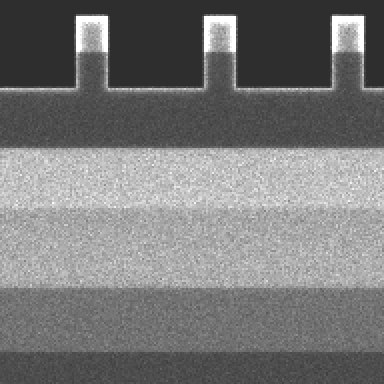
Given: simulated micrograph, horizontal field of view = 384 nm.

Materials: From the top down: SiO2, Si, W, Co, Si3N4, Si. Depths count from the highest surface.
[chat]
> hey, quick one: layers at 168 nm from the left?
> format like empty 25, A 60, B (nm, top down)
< empty 72, Si 60, W 60, Co 80, Si3N4 64, Si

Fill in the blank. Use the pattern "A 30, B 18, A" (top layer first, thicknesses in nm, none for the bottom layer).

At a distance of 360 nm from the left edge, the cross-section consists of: SiO2 36, Si 96, W 60, Co 80, Si3N4 64, Si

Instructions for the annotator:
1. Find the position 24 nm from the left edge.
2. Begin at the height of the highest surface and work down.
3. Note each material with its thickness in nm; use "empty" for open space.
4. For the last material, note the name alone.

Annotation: empty 72, Si 60, W 60, Co 80, Si3N4 64, Si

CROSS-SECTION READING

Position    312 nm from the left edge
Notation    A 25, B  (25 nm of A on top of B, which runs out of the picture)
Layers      empty 72, Si 60, W 60, Co 80, Si3N4 64, Si